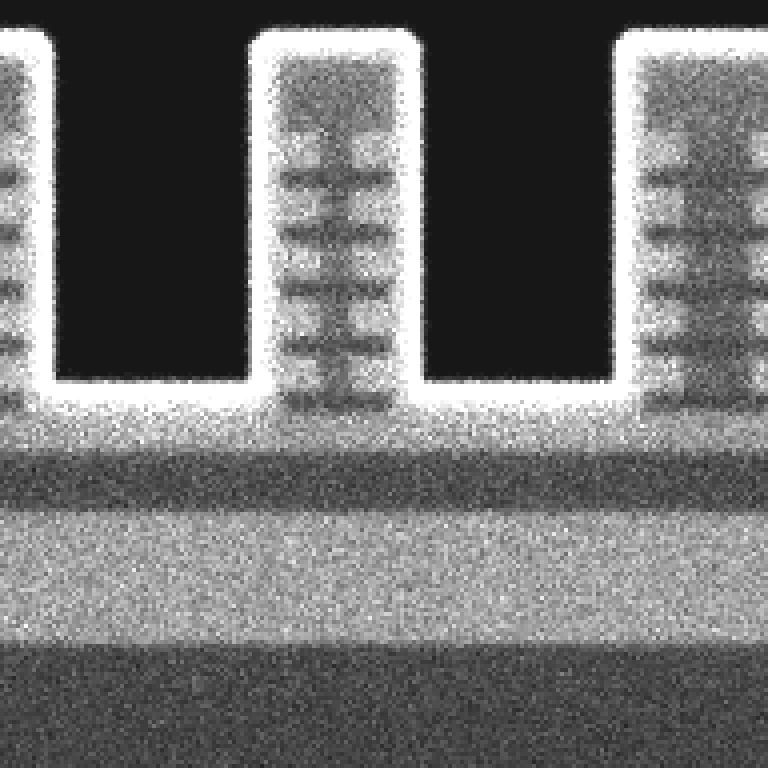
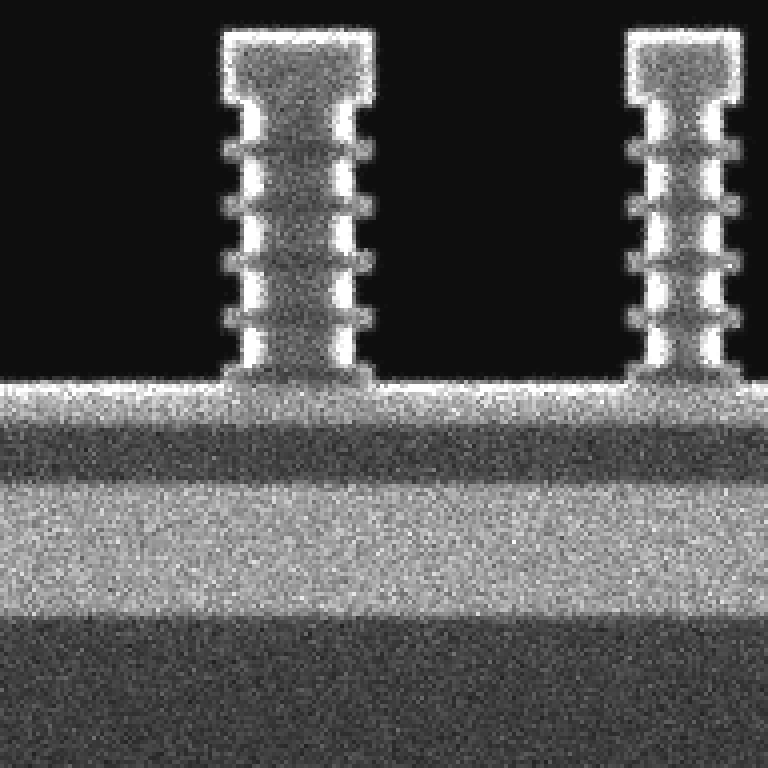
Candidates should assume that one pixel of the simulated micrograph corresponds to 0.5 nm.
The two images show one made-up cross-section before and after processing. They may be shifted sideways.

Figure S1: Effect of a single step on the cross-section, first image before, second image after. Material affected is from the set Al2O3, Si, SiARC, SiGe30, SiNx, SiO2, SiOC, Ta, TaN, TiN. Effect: removed Al2O3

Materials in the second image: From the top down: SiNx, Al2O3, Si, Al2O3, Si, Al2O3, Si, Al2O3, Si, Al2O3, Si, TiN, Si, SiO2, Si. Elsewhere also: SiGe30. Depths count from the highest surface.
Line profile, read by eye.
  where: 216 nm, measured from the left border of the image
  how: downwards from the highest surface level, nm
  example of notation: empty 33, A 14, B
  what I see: empty 176, TiN 20, Si 30, SiO2 66, Si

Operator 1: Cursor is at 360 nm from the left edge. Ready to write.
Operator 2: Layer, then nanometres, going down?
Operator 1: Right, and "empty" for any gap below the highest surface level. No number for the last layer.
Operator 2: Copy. SiNx 36, empty 18, Si 10, empty 18, Si 10, empty 18, Si 10, empty 18, Si 10, empty 18, Si 10, TiN 20, Si 30, SiO2 66, Si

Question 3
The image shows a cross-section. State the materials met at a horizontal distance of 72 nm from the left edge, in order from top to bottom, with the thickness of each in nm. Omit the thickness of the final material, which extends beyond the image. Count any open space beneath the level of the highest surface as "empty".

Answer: empty 176, TiN 20, Si 30, SiO2 66, Si